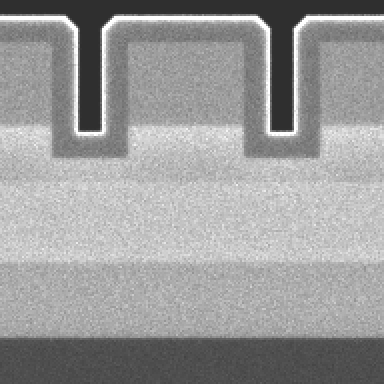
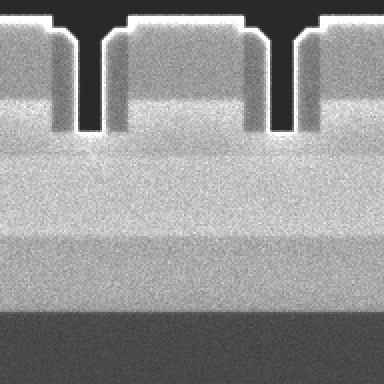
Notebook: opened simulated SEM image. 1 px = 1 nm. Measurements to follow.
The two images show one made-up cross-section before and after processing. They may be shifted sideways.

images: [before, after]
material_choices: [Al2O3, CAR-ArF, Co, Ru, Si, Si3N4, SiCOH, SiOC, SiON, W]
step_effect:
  removed: Si3N4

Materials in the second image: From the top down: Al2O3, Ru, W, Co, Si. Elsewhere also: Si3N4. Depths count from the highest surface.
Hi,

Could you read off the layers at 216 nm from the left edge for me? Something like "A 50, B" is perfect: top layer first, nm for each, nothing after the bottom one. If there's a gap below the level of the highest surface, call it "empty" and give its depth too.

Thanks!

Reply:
Al2O3 84, Ru 56, W 80, Co 76, Si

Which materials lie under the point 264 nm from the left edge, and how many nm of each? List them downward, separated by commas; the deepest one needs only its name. empty 20, Si3N4 96, Ru 24, W 80, Co 76, Si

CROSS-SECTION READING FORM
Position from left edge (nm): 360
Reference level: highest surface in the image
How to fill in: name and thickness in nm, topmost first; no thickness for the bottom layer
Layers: Al2O3 84, Ru 56, W 80, Co 76, Si